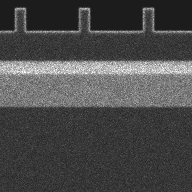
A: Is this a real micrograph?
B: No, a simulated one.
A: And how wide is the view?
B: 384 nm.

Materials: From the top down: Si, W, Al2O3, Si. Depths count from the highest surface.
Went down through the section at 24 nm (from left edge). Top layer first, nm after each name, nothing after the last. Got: empty 46, Si 60, W 26, Al2O3 66, Si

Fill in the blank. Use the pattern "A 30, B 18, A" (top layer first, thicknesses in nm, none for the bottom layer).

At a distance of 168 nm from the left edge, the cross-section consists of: Si 106, W 26, Al2O3 66, Si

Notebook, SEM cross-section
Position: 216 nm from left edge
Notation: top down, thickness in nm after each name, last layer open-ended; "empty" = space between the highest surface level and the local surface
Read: empty 46, Si 60, W 26, Al2O3 66, Si